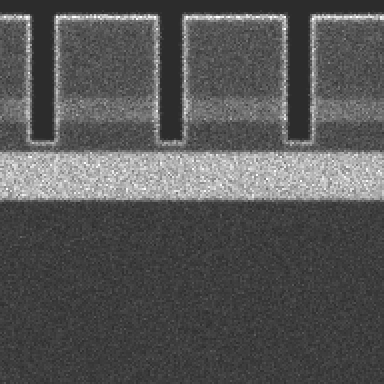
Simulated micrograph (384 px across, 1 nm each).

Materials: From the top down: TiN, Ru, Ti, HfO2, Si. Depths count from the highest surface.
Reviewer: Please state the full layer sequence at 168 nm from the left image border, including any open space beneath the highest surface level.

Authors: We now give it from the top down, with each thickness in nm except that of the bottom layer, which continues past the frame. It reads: empty 126, Ti 10, HfO2 48, Si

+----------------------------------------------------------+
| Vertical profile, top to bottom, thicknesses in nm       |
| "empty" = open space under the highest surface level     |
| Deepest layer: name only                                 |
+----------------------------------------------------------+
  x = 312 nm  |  TiN 82, Ru 24, Ti 30, HfO2 48, Si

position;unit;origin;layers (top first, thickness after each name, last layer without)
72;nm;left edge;TiN 82, Ru 24, Ti 30, HfO2 48, Si